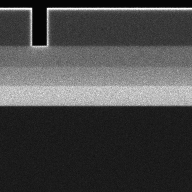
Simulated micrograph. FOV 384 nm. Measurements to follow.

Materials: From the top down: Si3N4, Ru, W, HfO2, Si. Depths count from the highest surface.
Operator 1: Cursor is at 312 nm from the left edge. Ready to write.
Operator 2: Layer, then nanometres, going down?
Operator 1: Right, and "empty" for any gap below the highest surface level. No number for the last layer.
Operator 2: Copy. Si3N4 76, Ru 42, W 38, HfO2 40, Si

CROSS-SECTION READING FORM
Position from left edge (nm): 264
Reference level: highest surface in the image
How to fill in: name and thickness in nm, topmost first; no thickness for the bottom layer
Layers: Si3N4 76, Ru 42, W 38, HfO2 40, Si